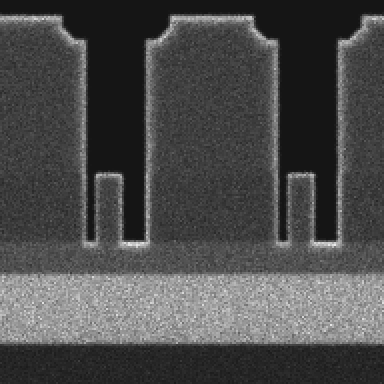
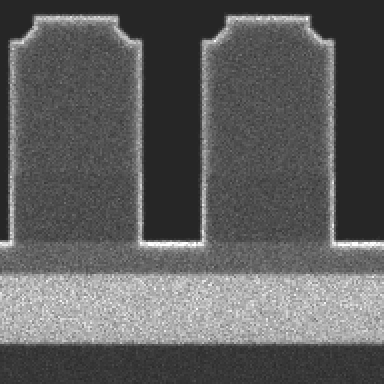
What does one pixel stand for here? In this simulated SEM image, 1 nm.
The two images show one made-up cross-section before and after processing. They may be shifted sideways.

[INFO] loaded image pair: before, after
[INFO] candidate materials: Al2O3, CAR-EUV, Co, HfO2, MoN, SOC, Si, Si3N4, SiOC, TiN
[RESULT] removed TiN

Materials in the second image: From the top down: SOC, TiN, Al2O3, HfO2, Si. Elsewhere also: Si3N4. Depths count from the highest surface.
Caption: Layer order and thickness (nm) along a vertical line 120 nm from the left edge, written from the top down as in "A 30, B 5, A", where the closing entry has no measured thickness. empty 14, SOC 144, Si3N4 68, Al2O3 32, HfO2 70, Si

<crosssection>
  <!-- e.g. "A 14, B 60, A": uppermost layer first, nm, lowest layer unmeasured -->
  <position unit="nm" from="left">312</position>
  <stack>empty 14, SOC 144, Si3N4 68, Al2O3 32, HfO2 70, Si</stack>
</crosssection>